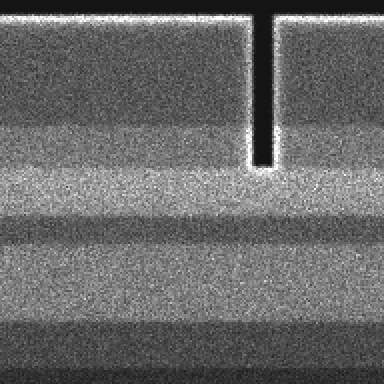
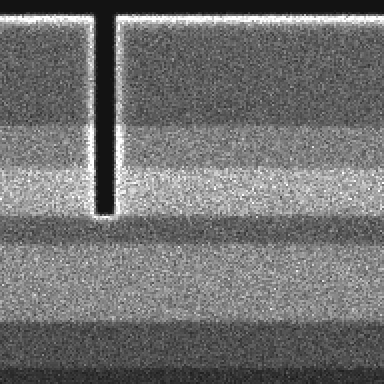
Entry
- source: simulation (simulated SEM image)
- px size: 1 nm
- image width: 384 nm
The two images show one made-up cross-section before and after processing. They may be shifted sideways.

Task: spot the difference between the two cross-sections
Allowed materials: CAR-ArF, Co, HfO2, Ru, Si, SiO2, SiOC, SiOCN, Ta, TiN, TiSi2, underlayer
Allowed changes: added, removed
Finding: removed Ru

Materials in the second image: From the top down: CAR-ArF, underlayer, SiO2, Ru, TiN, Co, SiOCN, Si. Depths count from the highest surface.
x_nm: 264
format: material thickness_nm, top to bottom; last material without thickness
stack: CAR-ArF 56, underlayer 54, SiO2 42, Ru 48, TiN 28, Co 78, SiOCN 46, Si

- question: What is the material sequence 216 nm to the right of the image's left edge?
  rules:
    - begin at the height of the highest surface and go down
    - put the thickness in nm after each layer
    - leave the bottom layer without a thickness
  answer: CAR-ArF 56, underlayer 54, SiO2 42, Ru 48, TiN 28, Co 78, SiOCN 46, Si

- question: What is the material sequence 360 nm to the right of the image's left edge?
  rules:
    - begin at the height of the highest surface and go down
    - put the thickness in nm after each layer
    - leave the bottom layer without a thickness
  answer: CAR-ArF 56, underlayer 54, SiO2 42, Ru 48, TiN 28, Co 78, SiOCN 46, Si